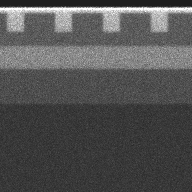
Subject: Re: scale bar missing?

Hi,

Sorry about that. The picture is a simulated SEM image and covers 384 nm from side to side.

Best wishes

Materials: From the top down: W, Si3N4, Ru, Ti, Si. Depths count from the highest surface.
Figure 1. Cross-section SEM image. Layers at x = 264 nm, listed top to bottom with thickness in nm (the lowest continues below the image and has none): W 10, Si3N4 66, Ru 46, Ti 70, Si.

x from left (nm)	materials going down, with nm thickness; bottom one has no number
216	W 48, Si3N4 28, Ru 46, Ti 70, Si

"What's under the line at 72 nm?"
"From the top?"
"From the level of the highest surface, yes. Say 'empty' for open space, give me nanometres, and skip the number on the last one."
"W 10, Si3N4 66, Ru 46, Ti 70, Si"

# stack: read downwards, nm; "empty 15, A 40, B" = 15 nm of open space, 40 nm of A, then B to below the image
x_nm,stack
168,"W 10, Si3N4 66, Ru 46, Ti 70, Si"